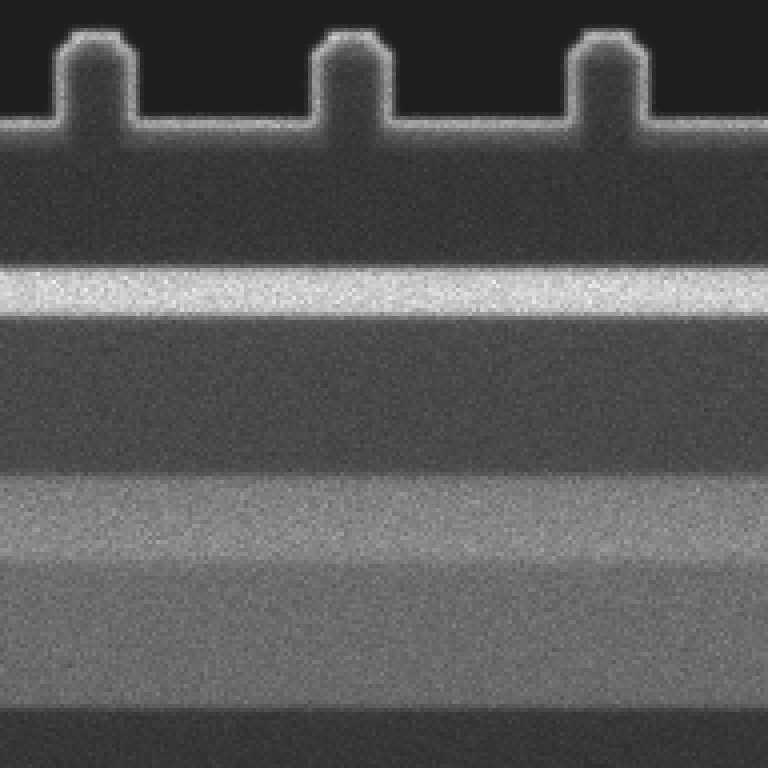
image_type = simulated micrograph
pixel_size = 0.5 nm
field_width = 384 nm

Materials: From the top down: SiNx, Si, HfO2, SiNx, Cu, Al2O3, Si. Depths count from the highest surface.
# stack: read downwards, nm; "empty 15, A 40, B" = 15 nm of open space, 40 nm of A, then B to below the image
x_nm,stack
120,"empty 44, SiNx 14, Si 60, HfO2 24, SiNx 80, Cu 42, Al2O3 74, Si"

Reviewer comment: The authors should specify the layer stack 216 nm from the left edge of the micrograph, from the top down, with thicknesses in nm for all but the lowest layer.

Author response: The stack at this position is empty 44, SiNx 14, Si 60, HfO2 24, SiNx 80, Cu 42, Al2O3 74, Si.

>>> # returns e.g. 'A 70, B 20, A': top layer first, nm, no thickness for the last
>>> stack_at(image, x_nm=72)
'empty 44, SiNx 14, Si 60, HfO2 24, SiNx 80, Cu 42, Al2O3 74, Si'